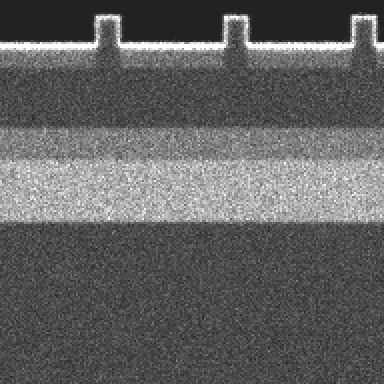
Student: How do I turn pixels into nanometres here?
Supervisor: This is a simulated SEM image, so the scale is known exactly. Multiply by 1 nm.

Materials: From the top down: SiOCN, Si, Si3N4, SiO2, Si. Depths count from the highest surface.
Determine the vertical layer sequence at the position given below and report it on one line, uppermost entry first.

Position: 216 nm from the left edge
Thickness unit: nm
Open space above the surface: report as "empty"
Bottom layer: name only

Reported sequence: empty 28, SiOCN 24, Si 60, Si3N4 32, SiO2 62, Si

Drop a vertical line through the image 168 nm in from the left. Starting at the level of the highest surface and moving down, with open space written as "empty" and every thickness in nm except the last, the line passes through empty 28, SiOCN 24, Si 60, Si3N4 32, SiO2 62, Si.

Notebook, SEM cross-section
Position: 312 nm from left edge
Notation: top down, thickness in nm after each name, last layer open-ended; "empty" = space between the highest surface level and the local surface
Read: empty 28, SiOCN 24, Si 60, Si3N4 32, SiO2 62, Si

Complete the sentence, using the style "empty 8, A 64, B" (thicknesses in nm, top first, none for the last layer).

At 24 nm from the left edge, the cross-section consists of empty 28, SiOCN 24, Si 60, Si3N4 32, SiO2 62, Si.